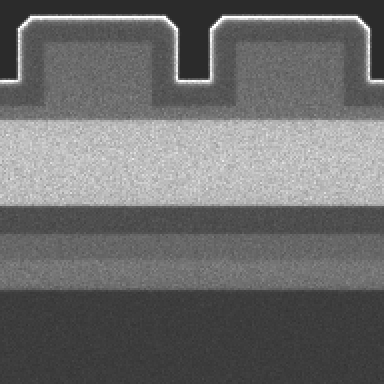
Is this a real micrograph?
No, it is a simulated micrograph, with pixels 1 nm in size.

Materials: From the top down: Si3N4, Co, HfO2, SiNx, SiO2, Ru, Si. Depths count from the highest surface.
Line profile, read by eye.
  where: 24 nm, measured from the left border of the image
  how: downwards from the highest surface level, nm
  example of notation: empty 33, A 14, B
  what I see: empty 6, Si3N4 84, Co 14, HfO2 86, SiNx 28, SiO2 26, Ru 30, Si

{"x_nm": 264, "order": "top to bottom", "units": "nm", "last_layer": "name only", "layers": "Si3N4 26, Co 78, HfO2 86, SiNx 28, SiO2 26, Ru 30, Si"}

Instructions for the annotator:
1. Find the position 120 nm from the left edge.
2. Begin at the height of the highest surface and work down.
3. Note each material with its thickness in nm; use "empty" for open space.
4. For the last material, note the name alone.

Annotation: Si3N4 26, Co 78, HfO2 86, SiNx 28, SiO2 26, Ru 30, Si